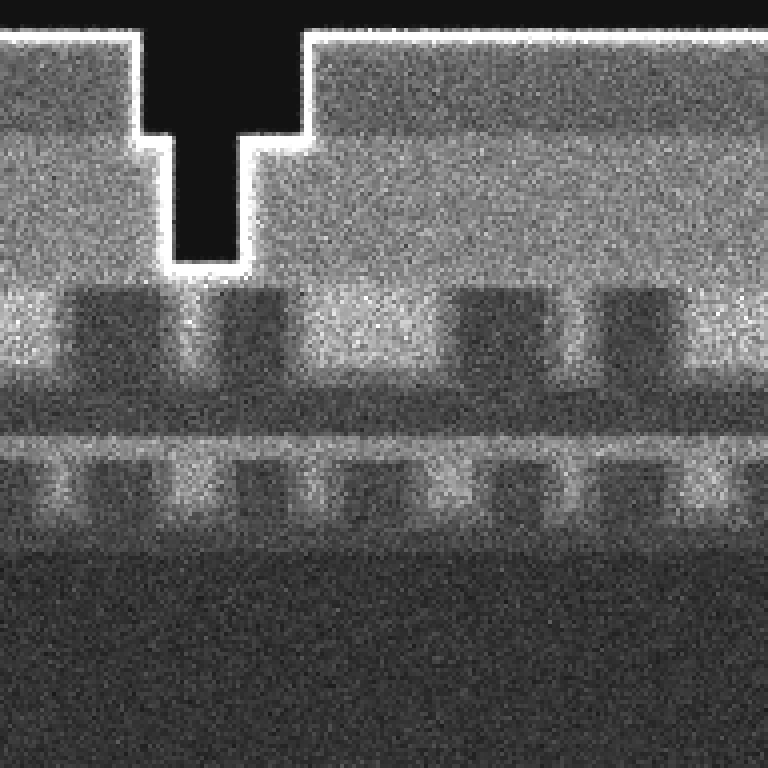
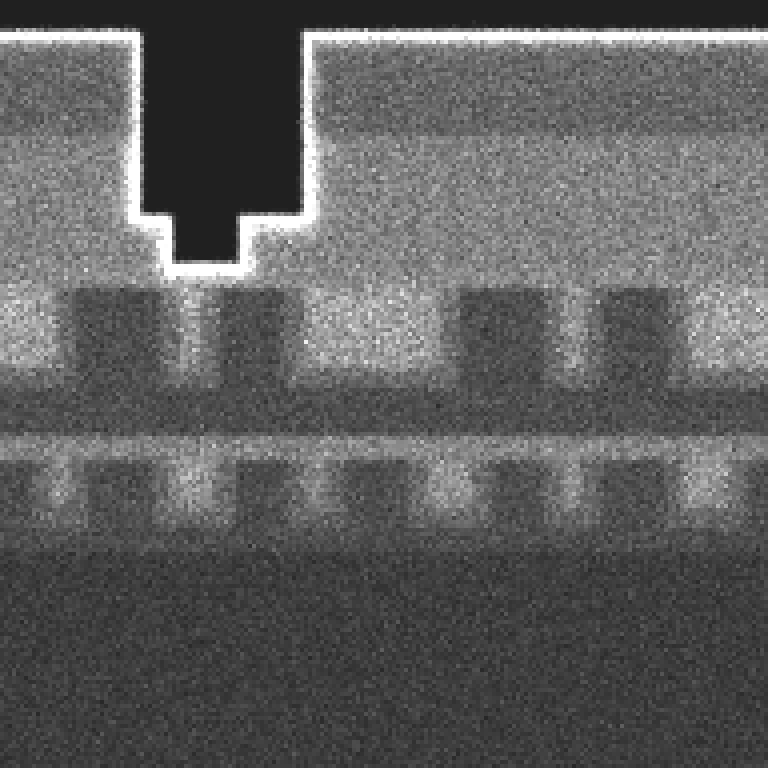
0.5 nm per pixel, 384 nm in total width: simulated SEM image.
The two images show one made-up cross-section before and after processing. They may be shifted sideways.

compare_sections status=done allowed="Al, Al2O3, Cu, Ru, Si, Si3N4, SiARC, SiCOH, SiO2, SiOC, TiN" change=removed material="SiO2"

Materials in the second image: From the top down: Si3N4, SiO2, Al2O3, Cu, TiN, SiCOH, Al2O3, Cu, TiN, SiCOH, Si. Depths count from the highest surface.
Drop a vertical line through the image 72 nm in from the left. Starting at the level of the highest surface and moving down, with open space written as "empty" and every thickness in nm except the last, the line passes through empty 92, SiO2 24, Al2O3 12, SiCOH 74, Al2O3 12, SiCOH 46, Si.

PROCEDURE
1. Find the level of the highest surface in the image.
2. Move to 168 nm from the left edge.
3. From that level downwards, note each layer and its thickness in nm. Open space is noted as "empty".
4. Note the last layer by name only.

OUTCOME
Si3N4 52, SiO2 64, Al2O3 12, Cu 40, TiN 10, SiCOH 24, Al2O3 12, TiN 34, SiCOH 12, Si